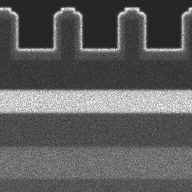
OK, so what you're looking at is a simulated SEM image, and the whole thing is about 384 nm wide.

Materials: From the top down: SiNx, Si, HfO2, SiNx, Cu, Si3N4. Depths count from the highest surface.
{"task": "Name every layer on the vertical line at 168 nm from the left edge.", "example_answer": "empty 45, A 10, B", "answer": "empty 82, SiNx 22, Si 60, HfO2 46, SiNx 68, Cu 64, Si3N4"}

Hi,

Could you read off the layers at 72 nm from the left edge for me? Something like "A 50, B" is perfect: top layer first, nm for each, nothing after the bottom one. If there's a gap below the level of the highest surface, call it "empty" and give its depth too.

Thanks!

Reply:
empty 82, SiNx 22, Si 60, HfO2 46, SiNx 68, Cu 64, Si3N4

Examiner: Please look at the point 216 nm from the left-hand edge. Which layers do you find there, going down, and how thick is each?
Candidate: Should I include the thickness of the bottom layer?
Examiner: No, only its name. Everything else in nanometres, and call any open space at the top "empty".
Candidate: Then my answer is empty 82, SiNx 22, Si 60, HfO2 46, SiNx 68, Cu 64, Si3N4